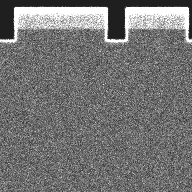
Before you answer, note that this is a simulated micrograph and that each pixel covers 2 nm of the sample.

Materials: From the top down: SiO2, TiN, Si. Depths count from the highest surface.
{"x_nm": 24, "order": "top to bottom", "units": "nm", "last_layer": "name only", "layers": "empty 64, Si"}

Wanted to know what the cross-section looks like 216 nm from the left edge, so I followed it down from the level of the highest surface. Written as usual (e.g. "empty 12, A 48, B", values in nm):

empty 64, Si